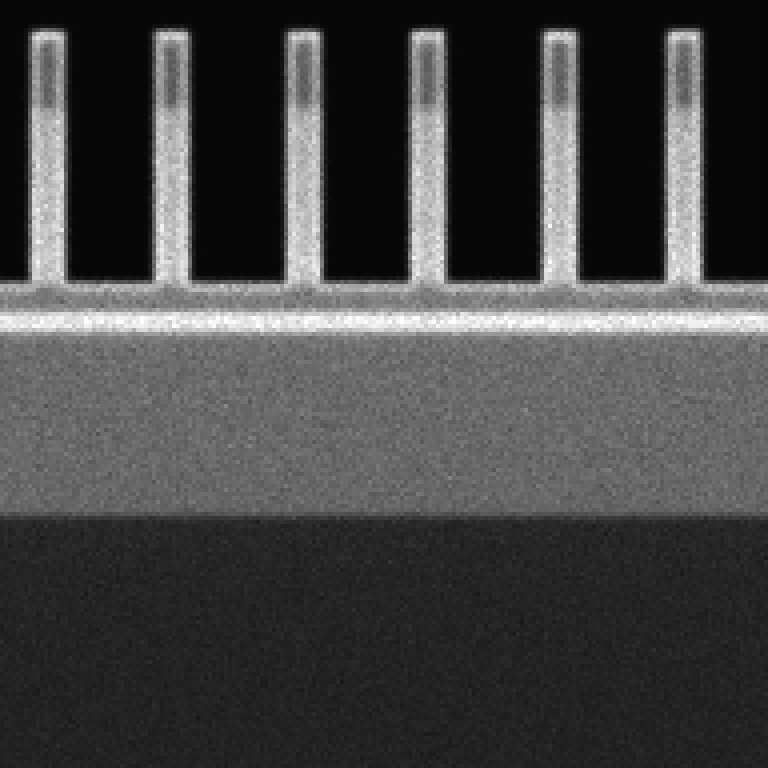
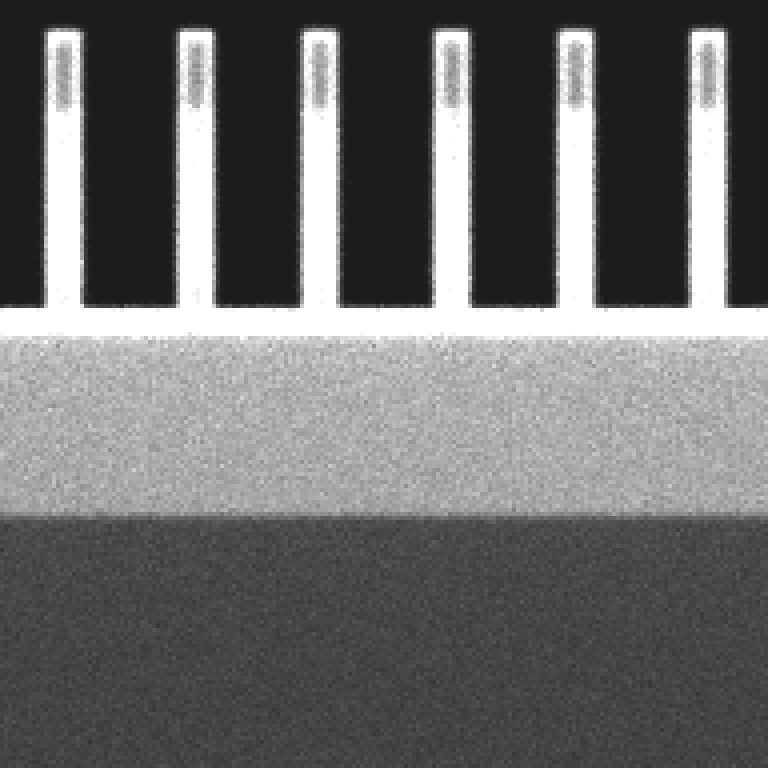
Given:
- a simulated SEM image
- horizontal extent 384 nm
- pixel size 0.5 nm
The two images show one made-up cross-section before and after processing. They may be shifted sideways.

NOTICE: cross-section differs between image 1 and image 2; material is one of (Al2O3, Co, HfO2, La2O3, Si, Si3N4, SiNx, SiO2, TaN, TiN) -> removed: TiN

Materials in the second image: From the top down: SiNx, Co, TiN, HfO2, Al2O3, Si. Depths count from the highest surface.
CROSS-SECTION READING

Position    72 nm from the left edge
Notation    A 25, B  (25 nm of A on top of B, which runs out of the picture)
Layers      empty 140, HfO2 10, Al2O3 92, Si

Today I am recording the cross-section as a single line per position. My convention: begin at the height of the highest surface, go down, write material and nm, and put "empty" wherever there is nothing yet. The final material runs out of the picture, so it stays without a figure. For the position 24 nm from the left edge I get SiNx 38, Co 88, TiN 14, HfO2 10, Al2O3 92, Si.